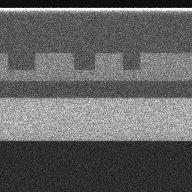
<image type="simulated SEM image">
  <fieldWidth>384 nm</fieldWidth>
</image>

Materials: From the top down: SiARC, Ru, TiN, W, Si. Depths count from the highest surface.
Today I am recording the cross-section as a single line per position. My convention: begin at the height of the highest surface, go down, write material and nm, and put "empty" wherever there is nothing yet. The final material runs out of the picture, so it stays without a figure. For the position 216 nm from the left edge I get SiARC 90, Ru 56, TiN 34, W 86, Si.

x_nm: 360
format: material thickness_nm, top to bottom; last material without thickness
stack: SiARC 90, Ru 56, TiN 34, W 86, Si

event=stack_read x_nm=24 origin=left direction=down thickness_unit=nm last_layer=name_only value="SiARC 124, Ru 22, TiN 34, W 86, Si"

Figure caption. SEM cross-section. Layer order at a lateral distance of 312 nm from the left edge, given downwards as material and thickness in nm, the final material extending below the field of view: SiARC 90, Ru 56, TiN 34, W 86, Si